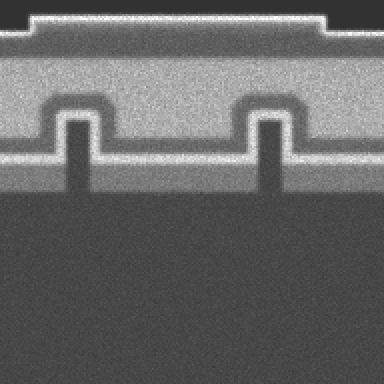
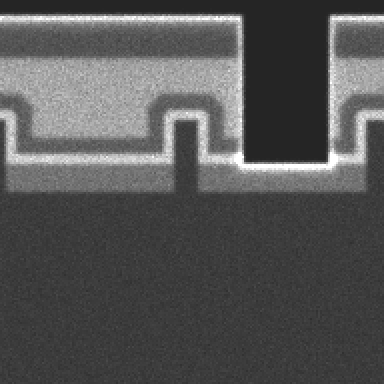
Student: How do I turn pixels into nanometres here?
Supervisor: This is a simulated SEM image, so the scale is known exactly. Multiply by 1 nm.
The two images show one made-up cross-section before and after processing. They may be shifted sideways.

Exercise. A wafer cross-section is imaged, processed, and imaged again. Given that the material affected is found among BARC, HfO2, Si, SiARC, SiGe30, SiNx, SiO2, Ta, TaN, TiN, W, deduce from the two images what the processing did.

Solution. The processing removed HfO2 and SiNx and TiN and W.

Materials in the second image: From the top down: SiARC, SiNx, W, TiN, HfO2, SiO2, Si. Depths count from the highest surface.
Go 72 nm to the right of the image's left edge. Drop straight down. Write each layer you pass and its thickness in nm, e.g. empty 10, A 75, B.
SiARC 16, SiNx 26, W 80, TiN 16, HfO2 10, SiO2 28, Si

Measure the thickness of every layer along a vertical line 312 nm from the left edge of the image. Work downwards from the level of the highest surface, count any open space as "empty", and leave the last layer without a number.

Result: empty 148, SiO2 28, Si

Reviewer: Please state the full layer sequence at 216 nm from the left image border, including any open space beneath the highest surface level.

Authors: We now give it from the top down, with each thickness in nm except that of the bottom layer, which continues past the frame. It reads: SiARC 16, SiNx 26, W 42, TiN 54, HfO2 10, SiO2 28, Si